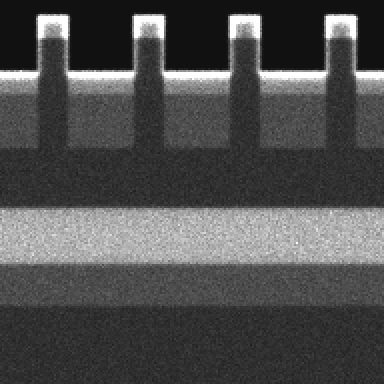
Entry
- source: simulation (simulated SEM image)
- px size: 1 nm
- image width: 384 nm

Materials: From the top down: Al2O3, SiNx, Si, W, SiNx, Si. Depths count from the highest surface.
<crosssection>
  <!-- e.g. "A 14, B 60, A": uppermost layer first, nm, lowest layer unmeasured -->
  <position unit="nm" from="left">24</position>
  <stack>empty 56, Al2O3 22, SiNx 54, Si 60, W 56, SiNx 42, Si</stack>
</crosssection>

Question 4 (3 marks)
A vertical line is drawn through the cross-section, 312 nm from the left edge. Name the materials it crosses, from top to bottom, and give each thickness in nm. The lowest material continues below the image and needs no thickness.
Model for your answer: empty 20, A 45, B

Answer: empty 56, Al2O3 22, SiNx 54, Si 60, W 56, SiNx 42, Si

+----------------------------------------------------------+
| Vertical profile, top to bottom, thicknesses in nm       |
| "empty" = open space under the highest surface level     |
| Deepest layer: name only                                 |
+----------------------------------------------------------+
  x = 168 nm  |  empty 56, Al2O3 22, SiNx 54, Si 60, W 56, SiNx 42, Si